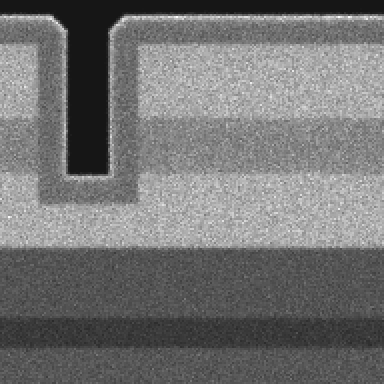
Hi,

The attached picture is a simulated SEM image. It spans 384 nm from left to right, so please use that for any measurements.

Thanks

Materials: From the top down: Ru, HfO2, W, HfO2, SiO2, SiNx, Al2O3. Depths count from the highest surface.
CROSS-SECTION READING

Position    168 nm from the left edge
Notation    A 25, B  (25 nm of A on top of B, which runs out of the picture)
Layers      Ru 28, HfO2 74, W 56, HfO2 74, SiO2 70, SiNx 30, Al2O3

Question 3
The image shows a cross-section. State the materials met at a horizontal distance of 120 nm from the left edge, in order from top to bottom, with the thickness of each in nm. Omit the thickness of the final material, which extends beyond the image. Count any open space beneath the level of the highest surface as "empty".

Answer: empty 4, Ru 184, HfO2 44, SiO2 70, SiNx 30, Al2O3